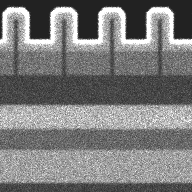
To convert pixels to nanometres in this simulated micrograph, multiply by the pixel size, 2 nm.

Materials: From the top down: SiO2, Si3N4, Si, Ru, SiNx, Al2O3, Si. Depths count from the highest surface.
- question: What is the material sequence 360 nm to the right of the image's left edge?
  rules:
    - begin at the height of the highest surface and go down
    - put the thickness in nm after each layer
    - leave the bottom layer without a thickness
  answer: empty 64, SiO2 22, Si3N4 48, Si 60, Ru 48, SiNx 42, Al2O3 66, Si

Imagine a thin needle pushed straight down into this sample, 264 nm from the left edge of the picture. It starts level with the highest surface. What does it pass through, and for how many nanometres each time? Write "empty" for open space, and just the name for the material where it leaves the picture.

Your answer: empty 64, SiO2 22, Si3N4 48, Si 60, Ru 48, SiNx 42, Al2O3 66, Si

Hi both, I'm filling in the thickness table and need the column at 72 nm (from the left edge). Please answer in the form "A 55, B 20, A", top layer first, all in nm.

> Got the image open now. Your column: empty 64, SiO2 22, Si3N4 48, Si 60, Ru 48, SiNx 42, Al2O3 66, Si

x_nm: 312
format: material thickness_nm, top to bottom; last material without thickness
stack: SiO2 86, Si3N4 48, Si 60, Ru 48, SiNx 42, Al2O3 66, Si